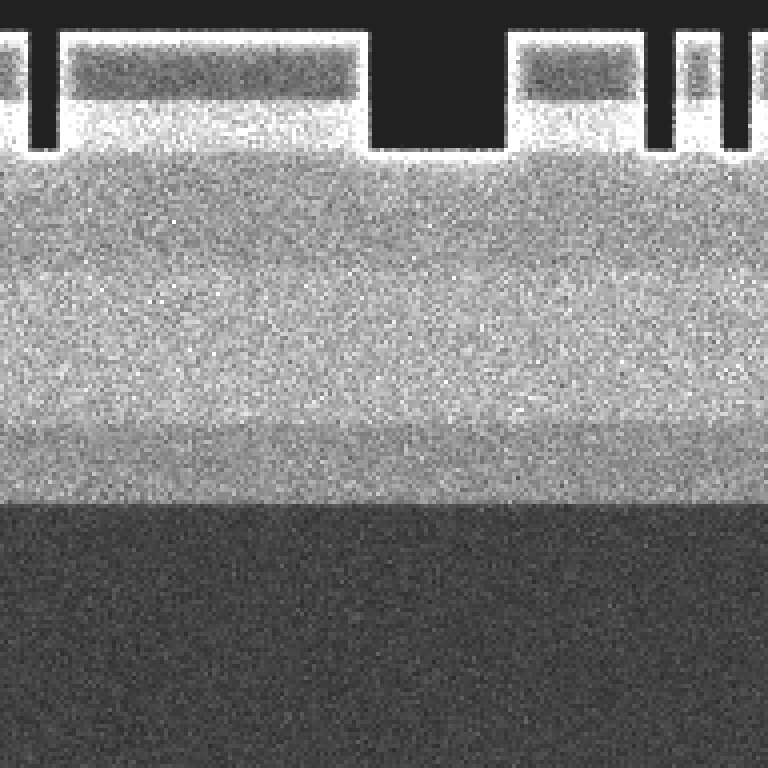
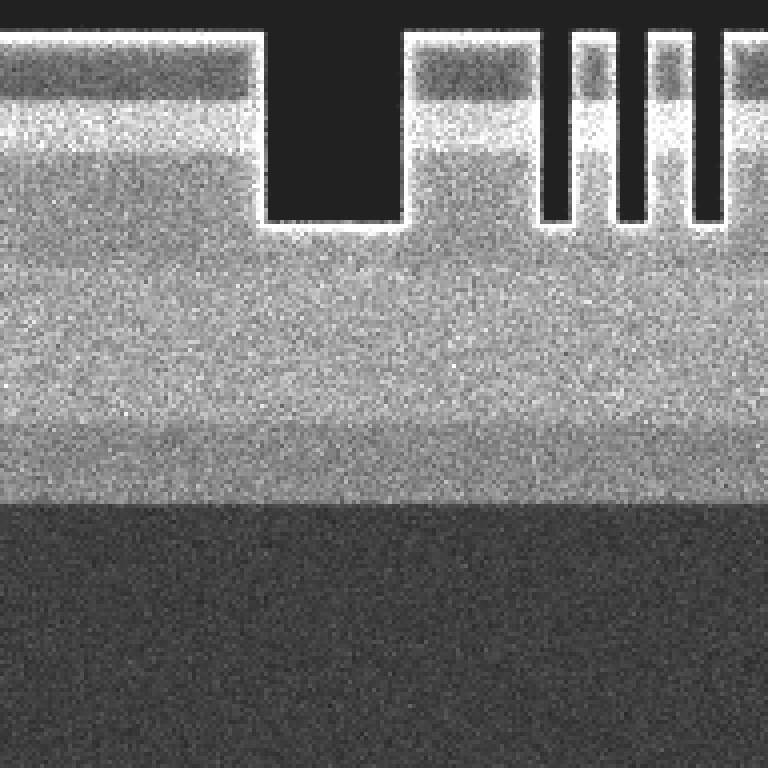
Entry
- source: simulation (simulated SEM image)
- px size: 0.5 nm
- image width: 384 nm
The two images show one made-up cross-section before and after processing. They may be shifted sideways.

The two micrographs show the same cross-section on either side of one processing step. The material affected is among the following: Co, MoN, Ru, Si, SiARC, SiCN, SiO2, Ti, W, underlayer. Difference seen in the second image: Co removed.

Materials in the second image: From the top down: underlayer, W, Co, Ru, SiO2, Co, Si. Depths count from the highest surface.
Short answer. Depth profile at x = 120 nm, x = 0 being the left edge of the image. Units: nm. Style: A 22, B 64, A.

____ underlayer 34, W 26, Co 58, Ru 78, SiO2 28, Co 12, Si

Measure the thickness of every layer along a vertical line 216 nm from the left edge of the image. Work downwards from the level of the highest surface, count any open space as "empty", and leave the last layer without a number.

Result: underlayer 34, W 26, Co 58, Ru 78, SiO2 28, Co 12, Si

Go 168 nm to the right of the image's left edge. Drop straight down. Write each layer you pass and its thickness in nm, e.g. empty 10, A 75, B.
empty 96, Co 22, Ru 78, SiO2 28, Co 12, Si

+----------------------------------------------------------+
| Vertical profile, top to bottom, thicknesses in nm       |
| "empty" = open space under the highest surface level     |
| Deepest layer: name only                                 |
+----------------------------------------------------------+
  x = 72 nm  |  underlayer 34, W 26, Co 58, Ru 78, SiO2 28, Co 12, Si